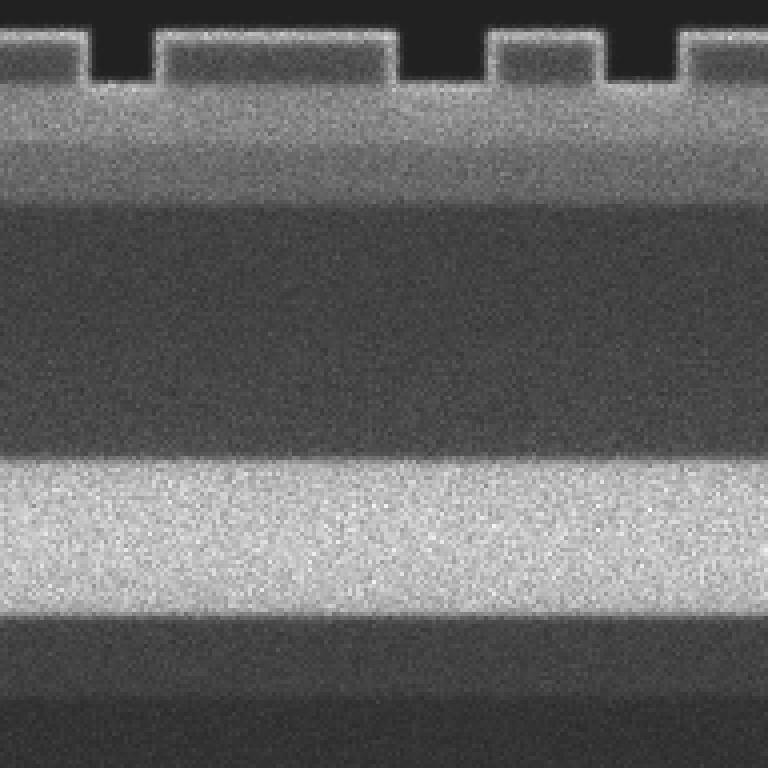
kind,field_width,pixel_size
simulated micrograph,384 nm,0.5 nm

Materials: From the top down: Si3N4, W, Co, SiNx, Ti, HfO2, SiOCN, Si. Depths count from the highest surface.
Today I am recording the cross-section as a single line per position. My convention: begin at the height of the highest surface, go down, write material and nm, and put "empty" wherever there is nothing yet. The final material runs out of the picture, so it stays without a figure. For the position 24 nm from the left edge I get Si3N4 26, W 30, Co 30, SiNx 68, Ti 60, HfO2 78, SiOCN 40, Si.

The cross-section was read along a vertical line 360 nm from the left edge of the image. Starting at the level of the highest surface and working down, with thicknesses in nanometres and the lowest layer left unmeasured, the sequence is Si3N4 26, W 30, Co 30, SiNx 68, Ti 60, HfO2 78, SiOCN 40, Si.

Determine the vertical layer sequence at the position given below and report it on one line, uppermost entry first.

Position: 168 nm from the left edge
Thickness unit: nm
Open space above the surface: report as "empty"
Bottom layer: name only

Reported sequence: Si3N4 26, W 30, Co 30, SiNx 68, Ti 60, HfO2 78, SiOCN 40, Si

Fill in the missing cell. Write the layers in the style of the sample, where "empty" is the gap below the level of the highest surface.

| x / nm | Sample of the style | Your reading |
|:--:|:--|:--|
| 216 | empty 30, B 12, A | empty 26, W 30, Co 30, SiNx 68, Ti 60, HfO2 78, SiOCN 40, Si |